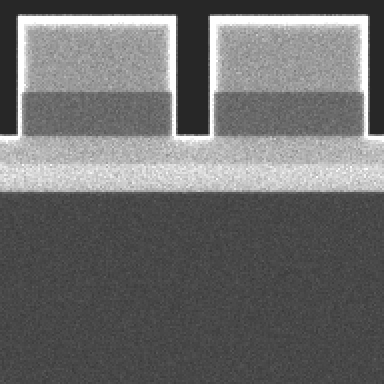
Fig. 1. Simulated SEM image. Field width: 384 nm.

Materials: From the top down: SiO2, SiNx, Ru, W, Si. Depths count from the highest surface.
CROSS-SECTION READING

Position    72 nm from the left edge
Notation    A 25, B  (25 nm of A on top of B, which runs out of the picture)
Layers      SiO2 76, SiNx 44, Ru 28, W 28, Si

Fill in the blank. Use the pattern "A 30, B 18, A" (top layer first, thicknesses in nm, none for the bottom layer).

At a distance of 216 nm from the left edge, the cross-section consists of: SiO2 76, SiNx 44, Ru 28, W 28, Si